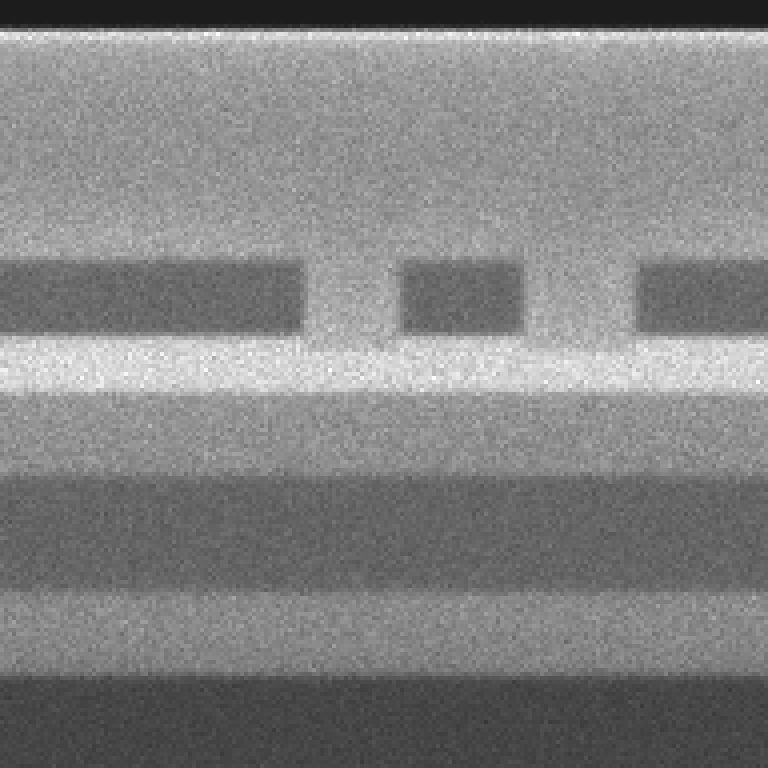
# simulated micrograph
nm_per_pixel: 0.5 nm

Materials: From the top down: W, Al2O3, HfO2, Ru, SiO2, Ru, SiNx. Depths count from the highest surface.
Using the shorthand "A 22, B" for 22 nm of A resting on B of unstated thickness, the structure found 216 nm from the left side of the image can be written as W 114, Al2O3 38, HfO2 28, Ru 42, SiO2 58, Ru 42, SiNx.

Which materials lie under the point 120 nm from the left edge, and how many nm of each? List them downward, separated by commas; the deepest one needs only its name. W 114, Al2O3 38, HfO2 28, Ru 42, SiO2 58, Ru 42, SiNx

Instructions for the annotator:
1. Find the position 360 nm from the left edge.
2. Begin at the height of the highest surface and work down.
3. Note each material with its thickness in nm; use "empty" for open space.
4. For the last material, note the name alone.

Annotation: W 114, Al2O3 38, HfO2 28, Ru 42, SiO2 58, Ru 42, SiNx